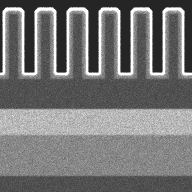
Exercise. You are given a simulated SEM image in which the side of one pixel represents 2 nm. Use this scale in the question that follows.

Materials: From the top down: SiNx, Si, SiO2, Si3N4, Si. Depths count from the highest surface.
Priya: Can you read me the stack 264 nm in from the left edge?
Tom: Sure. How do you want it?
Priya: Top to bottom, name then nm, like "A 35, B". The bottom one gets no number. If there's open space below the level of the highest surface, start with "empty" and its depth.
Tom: empty 4, SiNx 138, Si 60, SiO2 52, Si3N4 82, Si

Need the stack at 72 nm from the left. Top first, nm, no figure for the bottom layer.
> empty 4, SiNx 138, Si 60, SiO2 52, Si3N4 82, Si